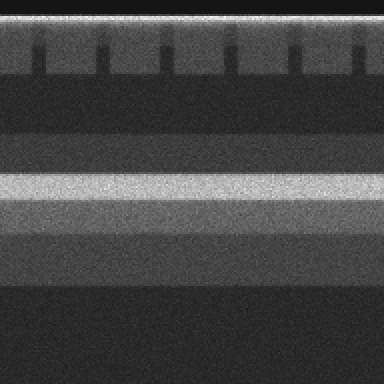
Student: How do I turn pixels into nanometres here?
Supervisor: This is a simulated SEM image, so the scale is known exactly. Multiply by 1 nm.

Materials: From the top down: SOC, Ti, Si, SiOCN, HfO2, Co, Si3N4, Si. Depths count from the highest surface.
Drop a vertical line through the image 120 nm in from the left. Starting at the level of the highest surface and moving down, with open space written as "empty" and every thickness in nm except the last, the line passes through SOC 58, Si 60, SiOCN 40, HfO2 26, Co 34, Si3N4 52, Si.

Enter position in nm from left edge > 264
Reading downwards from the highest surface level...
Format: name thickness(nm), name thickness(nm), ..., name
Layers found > SOC 58, Si 60, SiOCN 40, HfO2 26, Co 34, Si3N4 52, Si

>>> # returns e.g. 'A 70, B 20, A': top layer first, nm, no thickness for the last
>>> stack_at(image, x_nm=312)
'SOC 58, Si 60, SiOCN 40, HfO2 26, Co 34, Si3N4 52, Si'